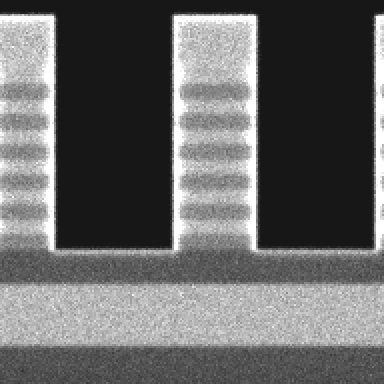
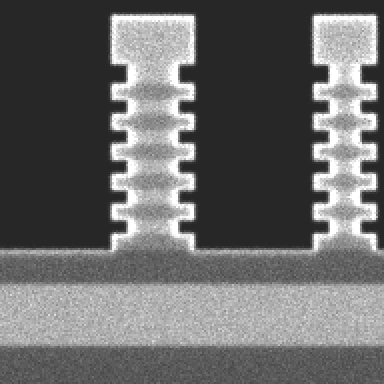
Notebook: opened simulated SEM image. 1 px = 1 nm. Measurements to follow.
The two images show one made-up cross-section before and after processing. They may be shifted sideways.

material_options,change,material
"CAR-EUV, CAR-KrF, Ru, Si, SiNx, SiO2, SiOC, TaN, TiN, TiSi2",removed,SiO2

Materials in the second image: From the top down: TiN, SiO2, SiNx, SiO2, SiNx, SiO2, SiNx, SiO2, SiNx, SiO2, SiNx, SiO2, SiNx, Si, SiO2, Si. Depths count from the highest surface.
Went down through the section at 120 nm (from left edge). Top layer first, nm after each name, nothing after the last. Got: TiN 48, empty 20, SiNx 16, empty 14, SiNx 16, empty 14, SiNx 16, empty 14, SiNx 16, empty 14, SiNx 16, empty 14, SiNx 16, Si 34, SiO2 62, Si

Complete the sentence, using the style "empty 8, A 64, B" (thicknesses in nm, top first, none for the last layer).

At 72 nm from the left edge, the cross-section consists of empty 234, Si 34, SiO2 62, Si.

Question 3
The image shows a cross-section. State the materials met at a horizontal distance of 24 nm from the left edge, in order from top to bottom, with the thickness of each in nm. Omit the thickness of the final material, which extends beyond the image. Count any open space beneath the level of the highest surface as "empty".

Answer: empty 234, Si 34, SiO2 62, Si